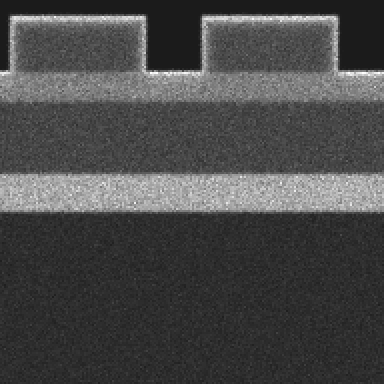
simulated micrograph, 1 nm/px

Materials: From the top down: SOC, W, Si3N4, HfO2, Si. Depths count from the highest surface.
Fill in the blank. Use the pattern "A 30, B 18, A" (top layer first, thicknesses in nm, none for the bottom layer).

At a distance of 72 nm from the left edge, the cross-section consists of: SOC 56, W 30, Si3N4 72, HfO2 38, Si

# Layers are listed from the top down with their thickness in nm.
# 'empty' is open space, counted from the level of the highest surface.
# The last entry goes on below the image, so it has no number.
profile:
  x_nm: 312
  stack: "SOC 56, W 30, Si3N4 72, HfO2 38, Si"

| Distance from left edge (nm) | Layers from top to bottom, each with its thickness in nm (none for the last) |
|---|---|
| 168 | empty 56, W 30, Si3N4 72, HfO2 38, Si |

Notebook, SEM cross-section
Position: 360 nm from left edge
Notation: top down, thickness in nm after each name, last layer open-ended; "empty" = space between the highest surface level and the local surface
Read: empty 56, W 30, Si3N4 72, HfO2 38, Si